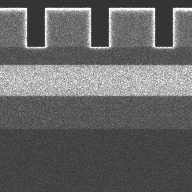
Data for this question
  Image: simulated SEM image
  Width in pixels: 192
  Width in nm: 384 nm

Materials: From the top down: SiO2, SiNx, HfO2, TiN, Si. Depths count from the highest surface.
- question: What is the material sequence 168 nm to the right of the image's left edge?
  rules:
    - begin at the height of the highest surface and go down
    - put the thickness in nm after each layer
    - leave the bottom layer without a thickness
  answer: SiO2 78, SiNx 36, HfO2 62, TiN 66, Si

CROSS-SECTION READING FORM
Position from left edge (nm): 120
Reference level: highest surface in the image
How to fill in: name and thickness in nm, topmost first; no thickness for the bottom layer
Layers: SiO2 78, SiNx 36, HfO2 62, TiN 66, Si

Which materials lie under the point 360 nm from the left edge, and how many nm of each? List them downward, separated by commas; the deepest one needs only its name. SiO2 78, SiNx 36, HfO2 62, TiN 66, Si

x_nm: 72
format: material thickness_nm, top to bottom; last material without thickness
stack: empty 78, SiNx 36, HfO2 62, TiN 66, Si